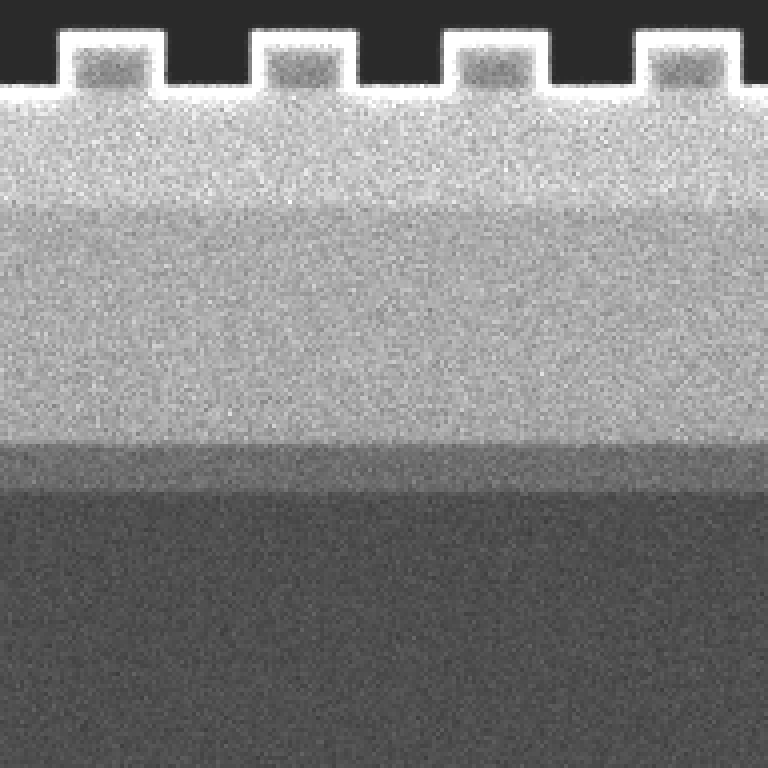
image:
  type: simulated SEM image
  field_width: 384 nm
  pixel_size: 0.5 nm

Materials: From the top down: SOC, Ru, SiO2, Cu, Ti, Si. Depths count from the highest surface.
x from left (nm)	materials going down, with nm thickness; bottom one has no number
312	empty 28, Ru 60, SiO2 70, Cu 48, Ti 24, Si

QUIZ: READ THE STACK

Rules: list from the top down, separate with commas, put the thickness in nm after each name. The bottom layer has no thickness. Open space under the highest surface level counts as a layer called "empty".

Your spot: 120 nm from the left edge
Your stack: empty 28, Ru 60, SiO2 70, Cu 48, Ti 24, Si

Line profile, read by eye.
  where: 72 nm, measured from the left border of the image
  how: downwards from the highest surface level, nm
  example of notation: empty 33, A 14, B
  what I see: SOC 28, Ru 60, SiO2 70, Cu 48, Ti 24, Si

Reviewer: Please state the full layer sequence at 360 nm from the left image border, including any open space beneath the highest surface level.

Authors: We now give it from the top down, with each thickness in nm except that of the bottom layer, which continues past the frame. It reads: SOC 28, Ru 60, SiO2 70, Cu 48, Ti 24, Si